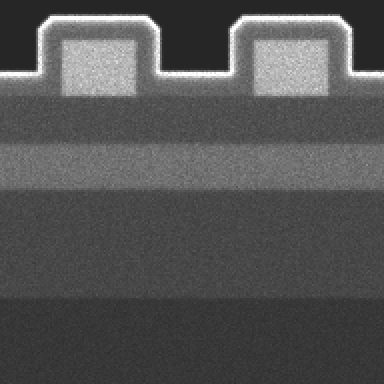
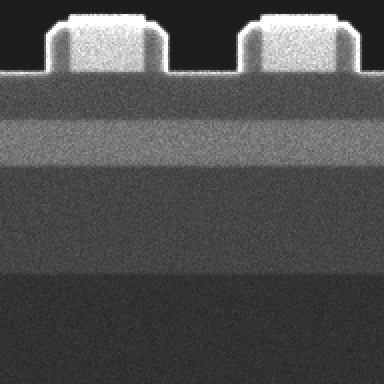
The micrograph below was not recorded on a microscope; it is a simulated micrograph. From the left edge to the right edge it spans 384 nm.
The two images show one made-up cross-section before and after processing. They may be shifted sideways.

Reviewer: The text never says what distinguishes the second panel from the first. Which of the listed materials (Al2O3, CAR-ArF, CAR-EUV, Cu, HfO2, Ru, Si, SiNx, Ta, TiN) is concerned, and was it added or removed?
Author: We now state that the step removed Al2O3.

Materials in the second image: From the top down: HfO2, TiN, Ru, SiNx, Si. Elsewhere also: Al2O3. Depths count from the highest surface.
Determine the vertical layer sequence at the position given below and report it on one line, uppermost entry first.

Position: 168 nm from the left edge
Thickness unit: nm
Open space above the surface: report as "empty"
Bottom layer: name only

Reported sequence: empty 56, TiN 48, Ru 46, SiNx 108, Si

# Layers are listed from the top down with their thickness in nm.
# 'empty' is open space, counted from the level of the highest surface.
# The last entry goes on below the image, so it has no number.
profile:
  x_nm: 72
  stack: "HfO2 56, TiN 48, Ru 46, SiNx 108, Si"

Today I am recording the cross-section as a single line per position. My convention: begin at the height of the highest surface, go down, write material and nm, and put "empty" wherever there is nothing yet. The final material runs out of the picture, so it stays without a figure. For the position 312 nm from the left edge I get HfO2 56, TiN 48, Ru 46, SiNx 108, Si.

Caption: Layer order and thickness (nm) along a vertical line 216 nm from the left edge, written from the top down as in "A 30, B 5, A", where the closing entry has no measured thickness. empty 56, TiN 48, Ru 46, SiNx 108, Si